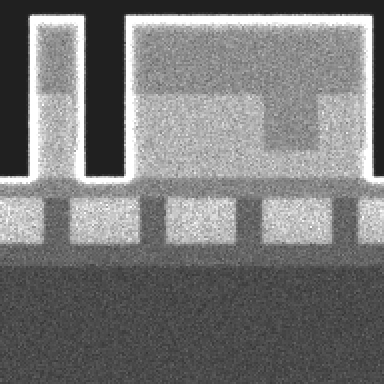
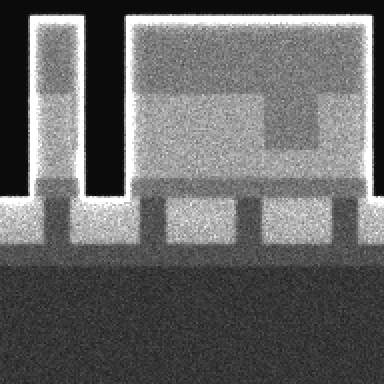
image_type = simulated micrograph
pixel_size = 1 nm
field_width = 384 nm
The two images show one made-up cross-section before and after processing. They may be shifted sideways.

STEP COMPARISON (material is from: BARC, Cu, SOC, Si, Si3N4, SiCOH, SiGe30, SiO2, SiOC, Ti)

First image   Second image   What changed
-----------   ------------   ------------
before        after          Si3N4, removed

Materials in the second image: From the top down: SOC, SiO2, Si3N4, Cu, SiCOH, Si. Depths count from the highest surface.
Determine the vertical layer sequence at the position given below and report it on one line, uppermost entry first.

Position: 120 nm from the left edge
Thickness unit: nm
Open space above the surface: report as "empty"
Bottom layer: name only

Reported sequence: empty 182, Cu 46, SiCOH 22, Si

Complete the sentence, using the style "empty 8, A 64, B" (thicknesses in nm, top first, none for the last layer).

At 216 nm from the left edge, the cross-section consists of SOC 78, SiO2 84, Si3N4 20, Cu 46, SiCOH 22, Si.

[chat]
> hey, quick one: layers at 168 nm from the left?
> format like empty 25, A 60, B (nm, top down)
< SOC 78, SiO2 84, Si3N4 20, Cu 46, SiCOH 22, Si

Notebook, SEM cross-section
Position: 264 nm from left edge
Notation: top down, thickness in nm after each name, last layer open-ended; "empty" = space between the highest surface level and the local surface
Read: SOC 134, SiO2 28, Si3N4 20, Cu 46, SiCOH 22, Si